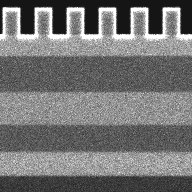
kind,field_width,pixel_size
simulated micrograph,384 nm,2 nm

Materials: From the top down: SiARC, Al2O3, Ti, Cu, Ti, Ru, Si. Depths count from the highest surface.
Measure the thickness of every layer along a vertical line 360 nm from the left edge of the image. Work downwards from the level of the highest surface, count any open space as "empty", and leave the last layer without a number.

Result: empty 54, Al2O3 42, Ti 72, Cu 66, Ti 54, Ru 48, Si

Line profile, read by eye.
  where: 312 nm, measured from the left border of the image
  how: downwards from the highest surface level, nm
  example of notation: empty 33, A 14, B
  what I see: empty 54, Al2O3 42, Ti 72, Cu 66, Ti 54, Ru 48, Si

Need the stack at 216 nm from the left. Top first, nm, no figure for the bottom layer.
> SiARC 54, Al2O3 42, Ti 72, Cu 66, Ti 54, Ru 48, Si